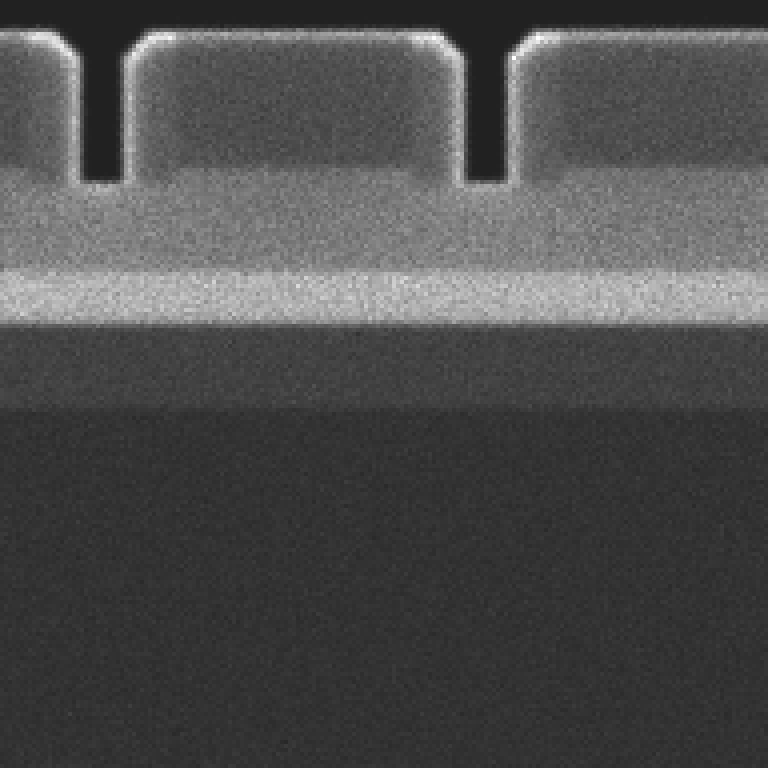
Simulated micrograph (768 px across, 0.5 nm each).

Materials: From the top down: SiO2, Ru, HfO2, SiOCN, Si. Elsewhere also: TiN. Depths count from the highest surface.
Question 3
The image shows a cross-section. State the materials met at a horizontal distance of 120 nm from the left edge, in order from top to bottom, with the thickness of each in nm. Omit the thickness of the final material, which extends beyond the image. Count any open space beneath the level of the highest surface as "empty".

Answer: TiN 68, Ru 52, HfO2 26, SiOCN 42, Si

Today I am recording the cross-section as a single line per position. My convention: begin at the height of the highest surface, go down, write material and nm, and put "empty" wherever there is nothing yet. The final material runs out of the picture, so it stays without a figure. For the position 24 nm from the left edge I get SiO2 76, Ru 44, HfO2 26, SiOCN 42, Si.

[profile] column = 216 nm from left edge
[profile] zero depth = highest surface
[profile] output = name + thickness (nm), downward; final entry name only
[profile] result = SiO2 76, Ru 44, HfO2 26, SiOCN 42, Si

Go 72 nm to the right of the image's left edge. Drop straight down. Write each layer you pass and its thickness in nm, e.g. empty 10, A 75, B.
empty 2, SiO2 74, Ru 44, HfO2 26, SiOCN 42, Si